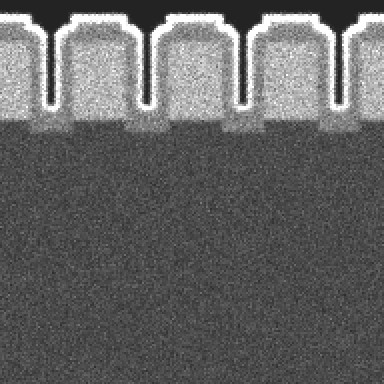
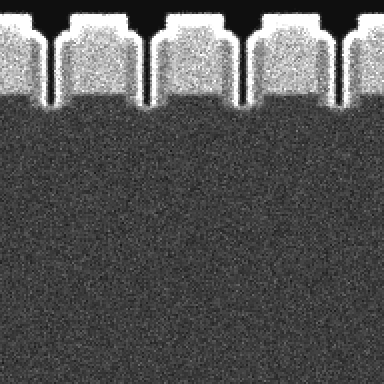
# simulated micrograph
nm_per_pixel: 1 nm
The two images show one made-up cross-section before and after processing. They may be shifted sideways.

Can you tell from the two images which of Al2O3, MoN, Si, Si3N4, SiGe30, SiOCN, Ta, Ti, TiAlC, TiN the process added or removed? Yes, it removed Si3N4.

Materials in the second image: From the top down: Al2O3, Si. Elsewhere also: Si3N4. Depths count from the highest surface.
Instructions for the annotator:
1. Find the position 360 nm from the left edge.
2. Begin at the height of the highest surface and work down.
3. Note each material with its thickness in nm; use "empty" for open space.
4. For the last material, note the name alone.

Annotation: Al2O3 78, Si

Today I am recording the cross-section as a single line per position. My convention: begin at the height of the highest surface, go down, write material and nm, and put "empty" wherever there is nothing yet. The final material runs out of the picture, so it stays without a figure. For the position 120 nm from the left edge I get Al2O3 78, Si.